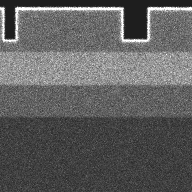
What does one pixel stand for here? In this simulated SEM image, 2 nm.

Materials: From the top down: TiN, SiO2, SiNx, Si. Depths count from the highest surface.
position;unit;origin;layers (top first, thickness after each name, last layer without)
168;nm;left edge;TiN 88, SiO2 66, SiNx 64, Si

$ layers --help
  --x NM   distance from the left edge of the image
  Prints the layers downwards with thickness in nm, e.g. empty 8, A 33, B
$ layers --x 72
TiN 88, SiO2 66, SiNx 64, Si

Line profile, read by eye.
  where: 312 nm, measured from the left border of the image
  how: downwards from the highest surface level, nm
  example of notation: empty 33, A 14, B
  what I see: TiN 88, SiO2 66, SiNx 64, Si